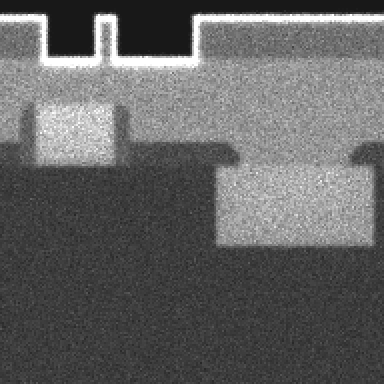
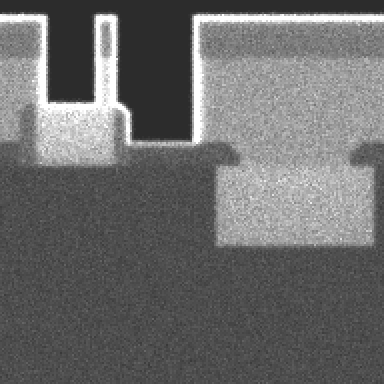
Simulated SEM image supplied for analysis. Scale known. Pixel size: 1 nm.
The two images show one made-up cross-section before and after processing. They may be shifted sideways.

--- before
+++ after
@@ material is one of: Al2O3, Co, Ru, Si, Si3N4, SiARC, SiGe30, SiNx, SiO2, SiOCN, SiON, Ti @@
SiO2 removed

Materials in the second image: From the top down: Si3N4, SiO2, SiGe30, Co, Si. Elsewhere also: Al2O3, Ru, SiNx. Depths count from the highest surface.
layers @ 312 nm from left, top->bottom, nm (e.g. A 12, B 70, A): Si3N4 42, SiO2 108, Co 80, Si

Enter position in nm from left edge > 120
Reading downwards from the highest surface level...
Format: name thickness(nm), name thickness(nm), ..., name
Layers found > empty 88, SiNx 62, Si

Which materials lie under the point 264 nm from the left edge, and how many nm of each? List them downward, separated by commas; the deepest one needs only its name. Si3N4 42, SiO2 108, Co 80, Si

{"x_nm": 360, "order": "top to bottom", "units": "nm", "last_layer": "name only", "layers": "Si3N4 42, SiO2 86, SiGe30 22, Co 80, Si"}